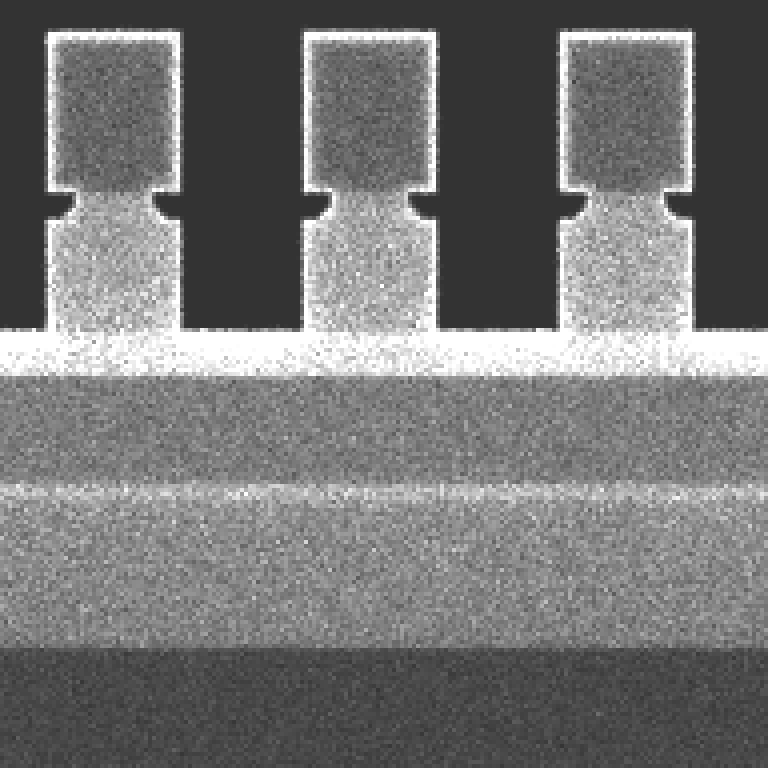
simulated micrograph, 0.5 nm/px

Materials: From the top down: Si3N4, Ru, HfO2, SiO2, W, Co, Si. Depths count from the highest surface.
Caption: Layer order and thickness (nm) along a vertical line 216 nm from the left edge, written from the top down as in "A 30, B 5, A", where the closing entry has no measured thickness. Si3N4 80, empty 14, Ru 56, HfO2 22, SiO2 54, W 8, Co 74, Si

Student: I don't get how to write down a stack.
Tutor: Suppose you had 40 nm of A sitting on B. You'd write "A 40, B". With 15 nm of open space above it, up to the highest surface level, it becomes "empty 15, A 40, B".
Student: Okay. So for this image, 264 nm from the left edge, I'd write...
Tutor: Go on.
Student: empty 150, HfO2 22, SiO2 54, W 8, Co 74, Si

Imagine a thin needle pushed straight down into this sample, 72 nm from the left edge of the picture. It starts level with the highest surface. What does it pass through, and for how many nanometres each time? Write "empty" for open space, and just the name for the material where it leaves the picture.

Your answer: Si3N4 80, Ru 70, HfO2 22, SiO2 54, W 8, Co 74, Si